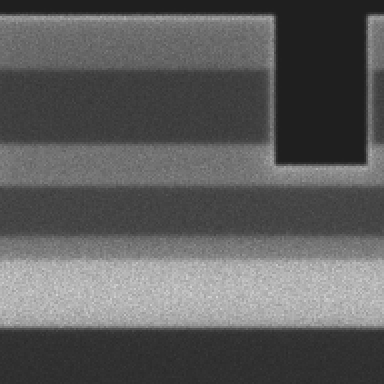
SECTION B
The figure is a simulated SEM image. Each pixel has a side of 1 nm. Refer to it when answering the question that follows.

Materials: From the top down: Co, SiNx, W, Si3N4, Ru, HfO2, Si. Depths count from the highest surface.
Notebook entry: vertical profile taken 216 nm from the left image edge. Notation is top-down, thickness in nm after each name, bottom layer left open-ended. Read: Co 54, SiNx 74, W 42, Si3N4 50, Ru 24, HfO2 68, Si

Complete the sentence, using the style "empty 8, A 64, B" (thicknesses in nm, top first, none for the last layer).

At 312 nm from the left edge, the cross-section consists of empty 150, W 20, Si3N4 50, Ru 24, HfO2 68, Si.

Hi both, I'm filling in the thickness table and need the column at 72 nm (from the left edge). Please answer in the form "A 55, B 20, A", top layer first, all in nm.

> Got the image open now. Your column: Co 54, SiNx 74, W 42, Si3N4 50, Ru 24, HfO2 68, Si